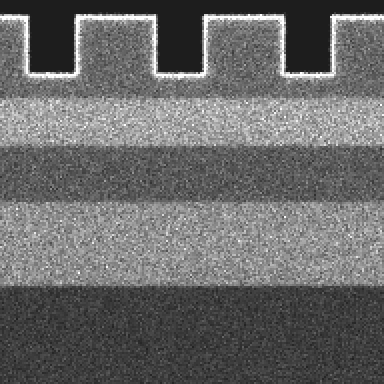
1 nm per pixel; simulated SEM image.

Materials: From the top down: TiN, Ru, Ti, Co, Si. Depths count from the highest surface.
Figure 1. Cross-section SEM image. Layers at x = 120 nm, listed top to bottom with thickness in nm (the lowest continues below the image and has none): TiN 82, Ru 48, Ti 56, Co 84, Si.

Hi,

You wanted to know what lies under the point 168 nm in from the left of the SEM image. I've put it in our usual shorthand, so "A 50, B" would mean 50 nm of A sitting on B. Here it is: empty 58, TiN 24, Ru 48, Ti 56, Co 84, Si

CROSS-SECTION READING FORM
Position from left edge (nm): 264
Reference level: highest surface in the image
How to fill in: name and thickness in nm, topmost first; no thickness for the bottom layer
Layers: TiN 82, Ru 48, Ti 56, Co 84, Si